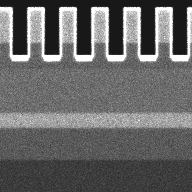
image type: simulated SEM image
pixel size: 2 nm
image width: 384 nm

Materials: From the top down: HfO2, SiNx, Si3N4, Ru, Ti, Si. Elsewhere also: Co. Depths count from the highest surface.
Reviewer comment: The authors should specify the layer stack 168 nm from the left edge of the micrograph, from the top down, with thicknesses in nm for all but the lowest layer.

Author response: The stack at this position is empty 96, HfO2 10, SiNx 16, Si3N4 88, Ru 30, Ti 64, Si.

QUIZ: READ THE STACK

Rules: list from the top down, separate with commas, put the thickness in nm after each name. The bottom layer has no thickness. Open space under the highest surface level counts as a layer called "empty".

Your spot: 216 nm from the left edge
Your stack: empty 96, HfO2 10, SiNx 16, Si3N4 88, Ru 30, Ti 64, Si